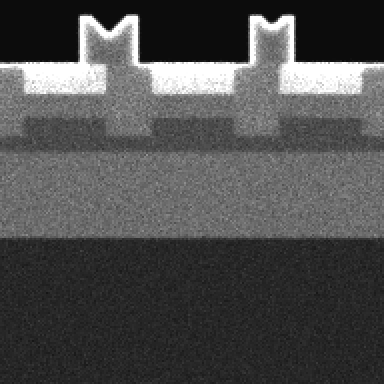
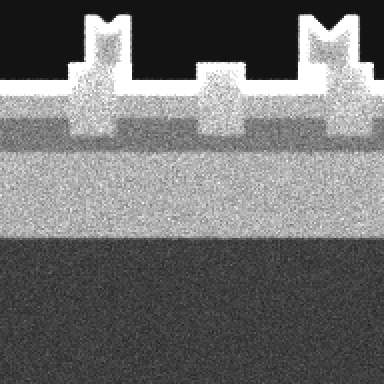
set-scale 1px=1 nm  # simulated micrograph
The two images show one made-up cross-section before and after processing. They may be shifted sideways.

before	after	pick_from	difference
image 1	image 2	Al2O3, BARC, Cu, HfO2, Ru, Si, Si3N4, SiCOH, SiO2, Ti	HfO2 removed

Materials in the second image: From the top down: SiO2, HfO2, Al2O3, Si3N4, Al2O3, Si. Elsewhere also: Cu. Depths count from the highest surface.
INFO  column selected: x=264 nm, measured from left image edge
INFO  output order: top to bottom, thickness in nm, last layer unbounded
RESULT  empty 66, HfO2 12, Al2O3 24, Si3N4 34, Al2O3 86, Si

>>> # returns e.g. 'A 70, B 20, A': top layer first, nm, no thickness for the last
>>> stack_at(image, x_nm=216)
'empty 48, Cu 72, Si3N4 16, Al2O3 86, Si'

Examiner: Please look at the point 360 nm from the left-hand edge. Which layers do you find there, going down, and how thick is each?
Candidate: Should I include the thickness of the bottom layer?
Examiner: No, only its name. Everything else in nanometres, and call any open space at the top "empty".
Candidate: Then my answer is empty 48, Cu 72, Si3N4 16, Al2O3 86, Si